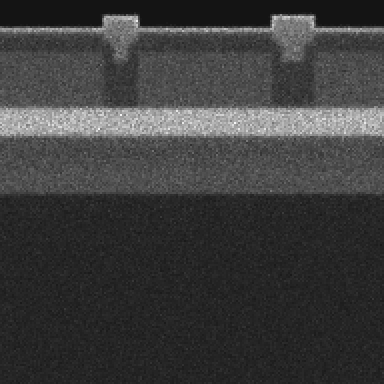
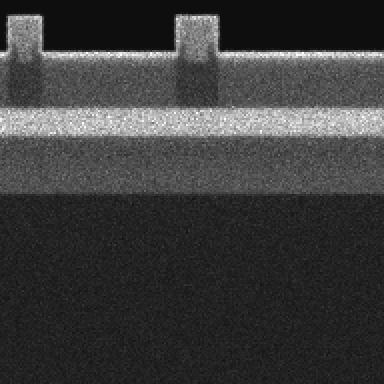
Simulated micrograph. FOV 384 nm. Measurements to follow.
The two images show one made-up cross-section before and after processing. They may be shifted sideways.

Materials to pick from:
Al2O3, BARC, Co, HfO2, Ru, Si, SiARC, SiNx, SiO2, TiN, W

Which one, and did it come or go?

SiNx - removed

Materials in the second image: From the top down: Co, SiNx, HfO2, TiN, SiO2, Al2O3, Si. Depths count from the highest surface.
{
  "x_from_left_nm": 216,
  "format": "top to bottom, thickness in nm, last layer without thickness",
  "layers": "Co 26, SiNx 66, HfO2 28, TiN 22, SiO2 12, Al2O3 24, Si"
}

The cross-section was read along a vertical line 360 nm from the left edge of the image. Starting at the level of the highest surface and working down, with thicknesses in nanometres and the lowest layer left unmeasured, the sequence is empty 36, SiO2 56, HfO2 28, TiN 22, SiO2 12, Al2O3 24, Si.